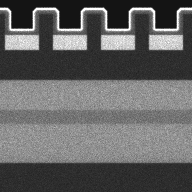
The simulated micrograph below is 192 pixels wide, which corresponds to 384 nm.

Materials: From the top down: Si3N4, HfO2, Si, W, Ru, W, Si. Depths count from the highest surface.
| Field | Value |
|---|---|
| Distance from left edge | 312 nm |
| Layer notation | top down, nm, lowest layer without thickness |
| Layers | empty 42, Si3N4 12, HfO2 30, Si 60, W 60, Ru 28, W 78, Si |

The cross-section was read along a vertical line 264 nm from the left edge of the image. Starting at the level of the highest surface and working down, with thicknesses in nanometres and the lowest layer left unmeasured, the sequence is Si3N4 54, HfO2 30, Si 60, W 60, Ru 28, W 78, Si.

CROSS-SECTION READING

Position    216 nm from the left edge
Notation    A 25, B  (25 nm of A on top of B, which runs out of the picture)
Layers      empty 42, Si3N4 12, HfO2 30, Si 60, W 60, Ru 28, W 78, Si